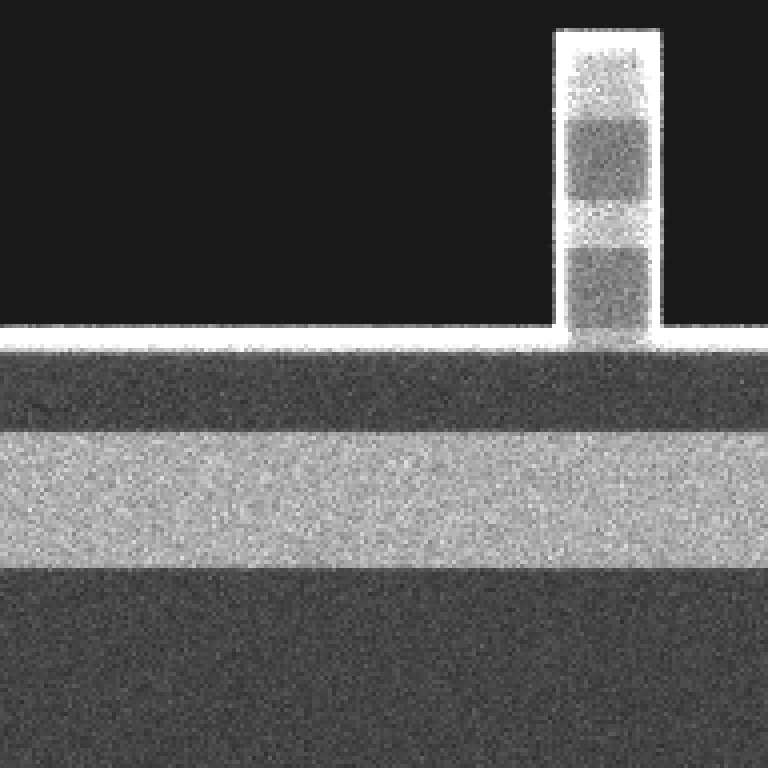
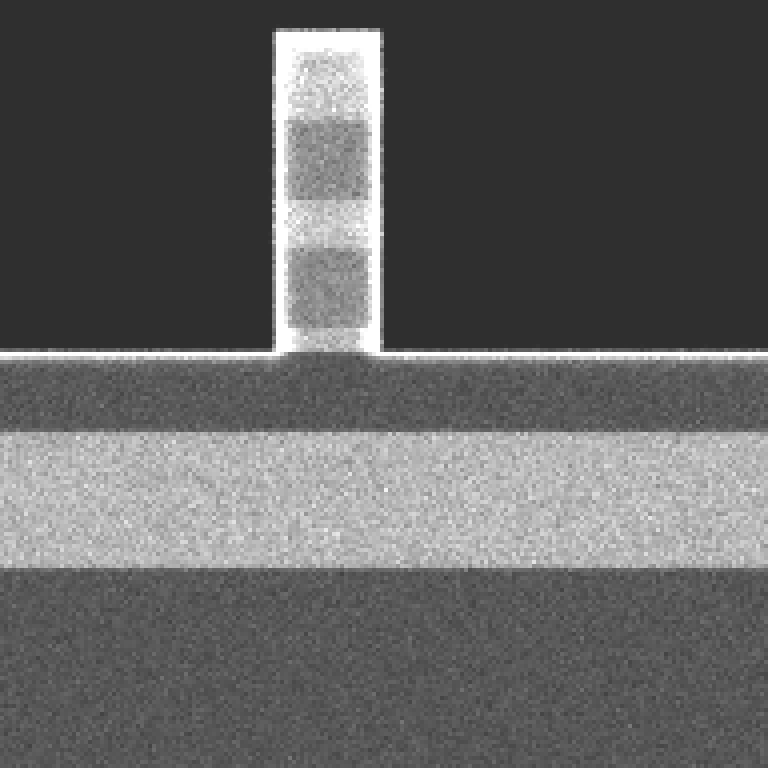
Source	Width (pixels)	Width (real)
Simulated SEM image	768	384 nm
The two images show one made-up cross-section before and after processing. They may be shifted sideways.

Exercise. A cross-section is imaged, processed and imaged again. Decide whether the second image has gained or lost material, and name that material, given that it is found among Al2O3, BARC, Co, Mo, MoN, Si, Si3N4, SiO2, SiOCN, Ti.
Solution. removed: SiO2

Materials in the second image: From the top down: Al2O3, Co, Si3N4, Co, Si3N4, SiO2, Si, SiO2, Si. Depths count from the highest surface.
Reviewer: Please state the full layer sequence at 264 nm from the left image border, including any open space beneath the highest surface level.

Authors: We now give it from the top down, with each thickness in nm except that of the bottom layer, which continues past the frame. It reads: empty 160, Si 40, SiO2 68, Si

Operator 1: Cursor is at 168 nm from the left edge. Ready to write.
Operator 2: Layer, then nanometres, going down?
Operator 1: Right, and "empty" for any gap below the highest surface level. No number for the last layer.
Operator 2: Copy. Al2O3 20, Co 24, Si3N4 40, Co 24, Si3N4 40, SiO2 12, Si 40, SiO2 68, Si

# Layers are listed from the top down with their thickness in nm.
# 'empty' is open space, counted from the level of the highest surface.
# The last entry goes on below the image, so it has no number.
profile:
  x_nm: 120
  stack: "empty 160, Si 40, SiO2 68, Si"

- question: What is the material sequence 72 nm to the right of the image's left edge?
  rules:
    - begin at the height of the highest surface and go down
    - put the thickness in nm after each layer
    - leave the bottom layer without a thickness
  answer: empty 160, Si 40, SiO2 68, Si